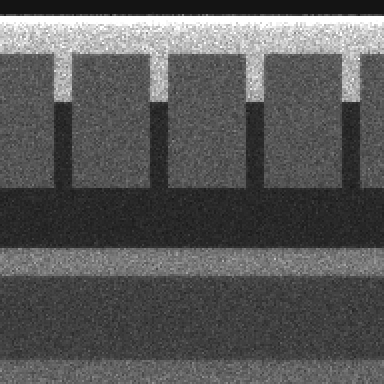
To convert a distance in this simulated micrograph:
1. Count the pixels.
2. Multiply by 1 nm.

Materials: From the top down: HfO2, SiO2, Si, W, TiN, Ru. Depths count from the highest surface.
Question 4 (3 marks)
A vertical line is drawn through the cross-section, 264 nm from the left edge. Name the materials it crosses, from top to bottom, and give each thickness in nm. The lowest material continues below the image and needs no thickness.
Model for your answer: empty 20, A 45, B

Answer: HfO2 38, SiO2 134, Si 60, W 28, TiN 84, Ru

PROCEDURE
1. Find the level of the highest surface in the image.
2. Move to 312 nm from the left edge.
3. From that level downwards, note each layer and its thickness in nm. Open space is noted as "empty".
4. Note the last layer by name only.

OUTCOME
HfO2 38, SiO2 134, Si 60, W 28, TiN 84, Ru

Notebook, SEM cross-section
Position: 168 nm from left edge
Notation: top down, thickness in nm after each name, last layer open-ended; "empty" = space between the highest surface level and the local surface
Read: HfO2 38, SiO2 134, Si 60, W 28, TiN 84, Ru